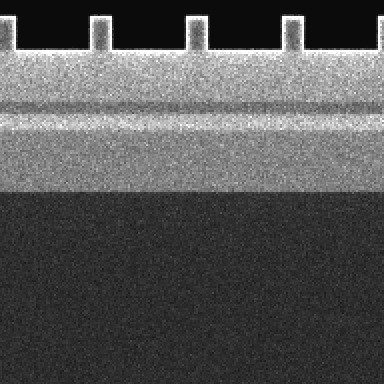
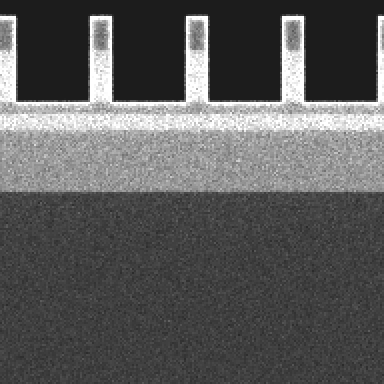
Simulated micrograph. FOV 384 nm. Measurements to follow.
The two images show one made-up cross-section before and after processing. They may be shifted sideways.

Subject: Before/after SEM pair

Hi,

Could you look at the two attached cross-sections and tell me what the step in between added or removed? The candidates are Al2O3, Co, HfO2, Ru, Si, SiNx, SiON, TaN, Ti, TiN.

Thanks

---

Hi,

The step removed Co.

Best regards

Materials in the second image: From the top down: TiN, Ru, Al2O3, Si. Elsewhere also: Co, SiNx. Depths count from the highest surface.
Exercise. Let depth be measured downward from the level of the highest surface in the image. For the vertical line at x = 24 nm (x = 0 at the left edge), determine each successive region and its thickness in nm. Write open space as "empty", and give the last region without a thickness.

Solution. empty 86, TiN 12, Ru 16, Al2O3 62, Si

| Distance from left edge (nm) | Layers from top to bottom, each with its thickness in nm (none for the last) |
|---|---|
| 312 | empty 86, TiN 12, Ru 16, Al2O3 62, Si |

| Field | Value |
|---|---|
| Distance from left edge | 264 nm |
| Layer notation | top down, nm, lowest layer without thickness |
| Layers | empty 86, TiN 12, Ru 16, Al2O3 62, Si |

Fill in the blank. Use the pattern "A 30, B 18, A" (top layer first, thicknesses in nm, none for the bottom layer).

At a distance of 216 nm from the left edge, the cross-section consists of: empty 86, TiN 12, Ru 16, Al2O3 62, Si